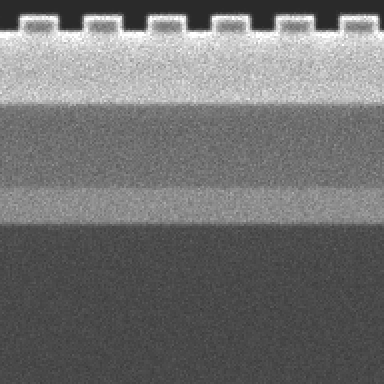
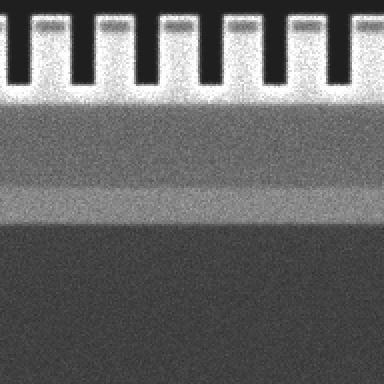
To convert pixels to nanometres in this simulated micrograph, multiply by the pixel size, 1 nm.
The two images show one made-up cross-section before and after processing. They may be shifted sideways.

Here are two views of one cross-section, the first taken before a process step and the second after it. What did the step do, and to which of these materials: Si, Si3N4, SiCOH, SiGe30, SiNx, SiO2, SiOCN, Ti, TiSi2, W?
It removed W.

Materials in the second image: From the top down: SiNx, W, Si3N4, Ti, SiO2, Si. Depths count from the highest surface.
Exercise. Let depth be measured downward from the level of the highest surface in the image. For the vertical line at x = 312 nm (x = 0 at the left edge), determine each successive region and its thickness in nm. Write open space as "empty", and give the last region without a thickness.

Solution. SiNx 16, W 72, Si3N4 14, Ti 70, SiO2 36, Si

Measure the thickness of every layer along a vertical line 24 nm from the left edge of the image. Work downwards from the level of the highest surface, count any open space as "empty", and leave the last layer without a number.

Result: empty 70, W 18, Si3N4 14, Ti 70, SiO2 36, Si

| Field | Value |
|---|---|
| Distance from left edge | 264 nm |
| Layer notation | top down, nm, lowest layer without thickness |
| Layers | empty 70, W 18, Si3N4 14, Ti 70, SiO2 36, Si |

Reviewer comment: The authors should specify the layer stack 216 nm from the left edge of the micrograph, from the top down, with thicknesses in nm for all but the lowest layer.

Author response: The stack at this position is empty 70, W 18, Si3N4 14, Ti 70, SiO2 36, Si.